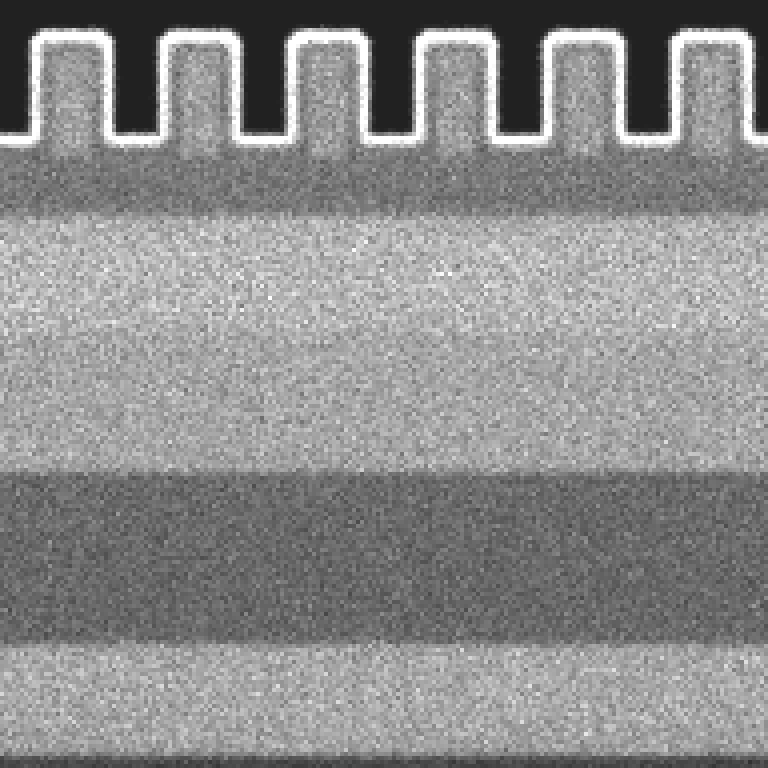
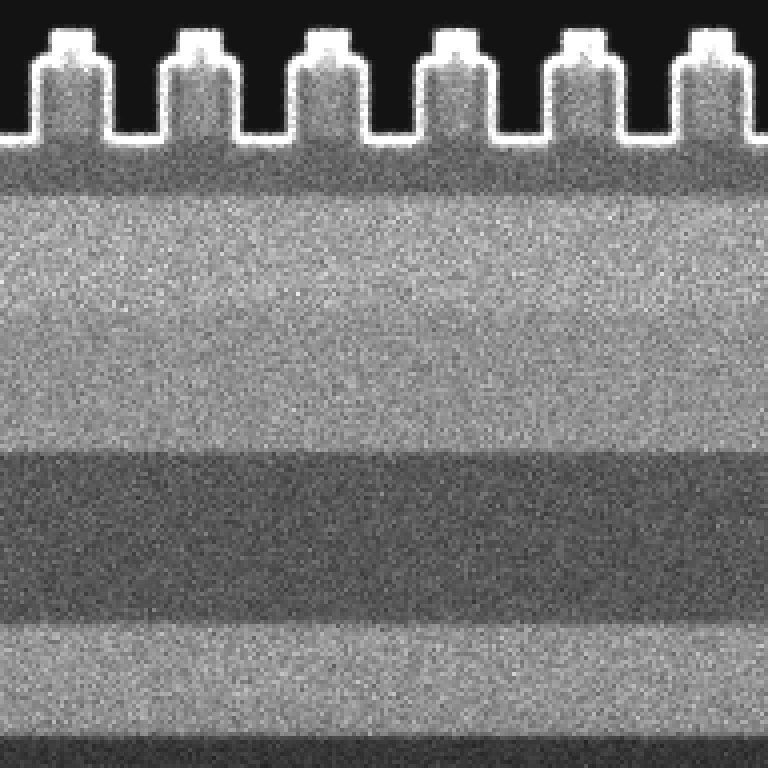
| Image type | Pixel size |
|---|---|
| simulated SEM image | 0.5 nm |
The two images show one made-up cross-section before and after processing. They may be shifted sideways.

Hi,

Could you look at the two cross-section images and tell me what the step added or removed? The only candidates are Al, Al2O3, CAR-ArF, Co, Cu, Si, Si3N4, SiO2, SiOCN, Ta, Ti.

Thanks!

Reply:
removed SiOCN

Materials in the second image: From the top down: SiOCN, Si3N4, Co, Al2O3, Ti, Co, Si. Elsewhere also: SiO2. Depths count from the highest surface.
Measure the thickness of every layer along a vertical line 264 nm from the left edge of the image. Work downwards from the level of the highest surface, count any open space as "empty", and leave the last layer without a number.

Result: empty 52, Si3N4 30, Co 58, Al2O3 70, Ti 86, Co 56, Si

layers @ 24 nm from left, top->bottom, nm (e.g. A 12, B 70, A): empty 12, SiOCN 40, Si3N4 30, Co 58, Al2O3 70, Ti 86, Co 56, Si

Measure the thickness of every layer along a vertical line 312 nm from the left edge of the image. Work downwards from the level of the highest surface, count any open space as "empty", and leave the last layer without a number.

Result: empty 52, Si3N4 30, Co 58, Al2O3 70, Ti 86, Co 56, Si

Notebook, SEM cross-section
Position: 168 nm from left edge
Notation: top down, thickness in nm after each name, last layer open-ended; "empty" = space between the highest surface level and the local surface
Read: SiO2 52, Si3N4 30, Co 58, Al2O3 70, Ti 86, Co 56, Si